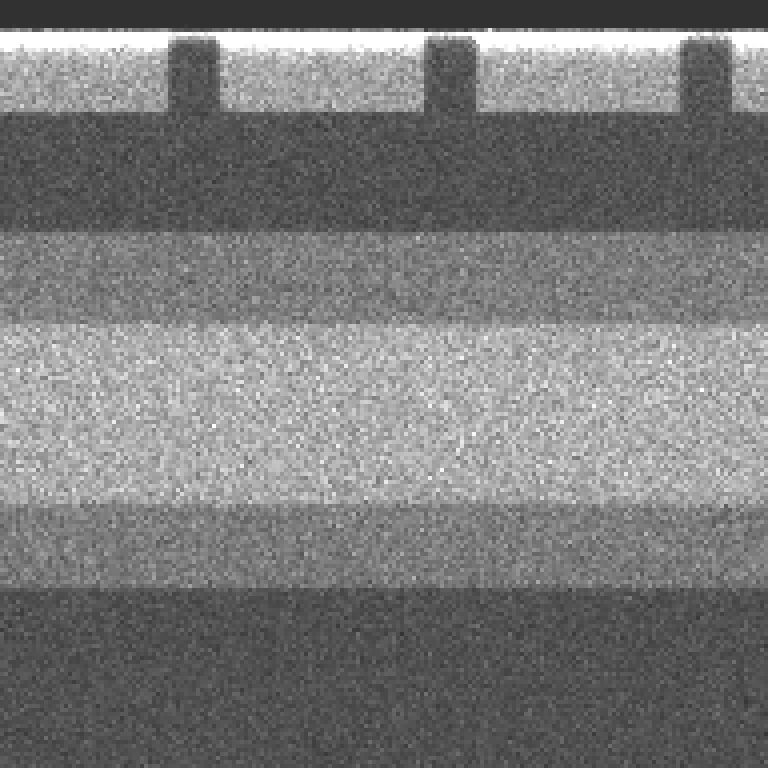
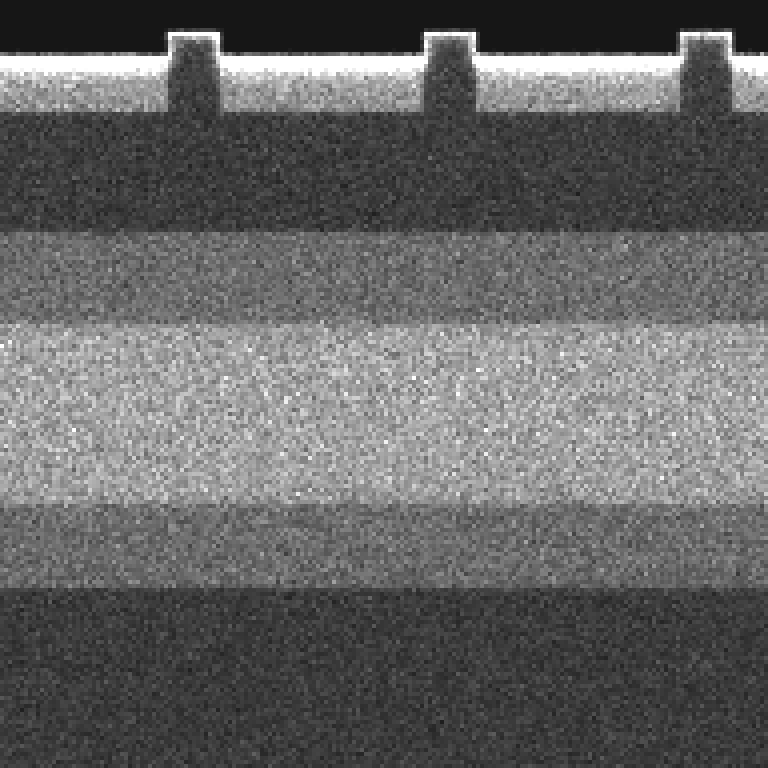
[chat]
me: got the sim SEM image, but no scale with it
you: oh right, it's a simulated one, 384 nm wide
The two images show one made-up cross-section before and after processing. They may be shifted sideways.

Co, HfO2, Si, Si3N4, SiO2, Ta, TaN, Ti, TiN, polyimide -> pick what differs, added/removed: SiO2 removed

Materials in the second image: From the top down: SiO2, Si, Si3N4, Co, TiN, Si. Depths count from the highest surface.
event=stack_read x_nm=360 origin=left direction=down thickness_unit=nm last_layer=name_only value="Si 100, Si3N4 46, Co 90, TiN 42, Si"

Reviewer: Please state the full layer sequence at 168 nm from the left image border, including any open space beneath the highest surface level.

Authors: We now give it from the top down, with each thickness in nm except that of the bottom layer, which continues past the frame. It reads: empty 12, SiO2 28, Si 60, Si3N4 46, Co 90, TiN 42, Si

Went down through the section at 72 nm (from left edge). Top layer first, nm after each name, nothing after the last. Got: empty 12, SiO2 28, Si 60, Si3N4 46, Co 90, TiN 42, Si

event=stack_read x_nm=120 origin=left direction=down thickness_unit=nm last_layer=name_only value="empty 12, SiO2 28, Si 60, Si3N4 46, Co 90, TiN 42, Si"